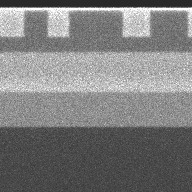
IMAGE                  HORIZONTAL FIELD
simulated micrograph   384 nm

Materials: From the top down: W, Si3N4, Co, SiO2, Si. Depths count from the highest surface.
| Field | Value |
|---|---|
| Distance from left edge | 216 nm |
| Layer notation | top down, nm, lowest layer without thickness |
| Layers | Si3N4 88, Co 80, SiO2 70, Si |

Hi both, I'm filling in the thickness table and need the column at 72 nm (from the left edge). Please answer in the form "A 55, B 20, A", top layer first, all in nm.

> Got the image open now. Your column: Si3N4 88, Co 80, SiO2 70, Si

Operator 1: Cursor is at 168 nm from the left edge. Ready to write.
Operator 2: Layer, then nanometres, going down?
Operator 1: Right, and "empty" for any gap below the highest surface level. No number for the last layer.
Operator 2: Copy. Si3N4 88, Co 80, SiO2 70, Si